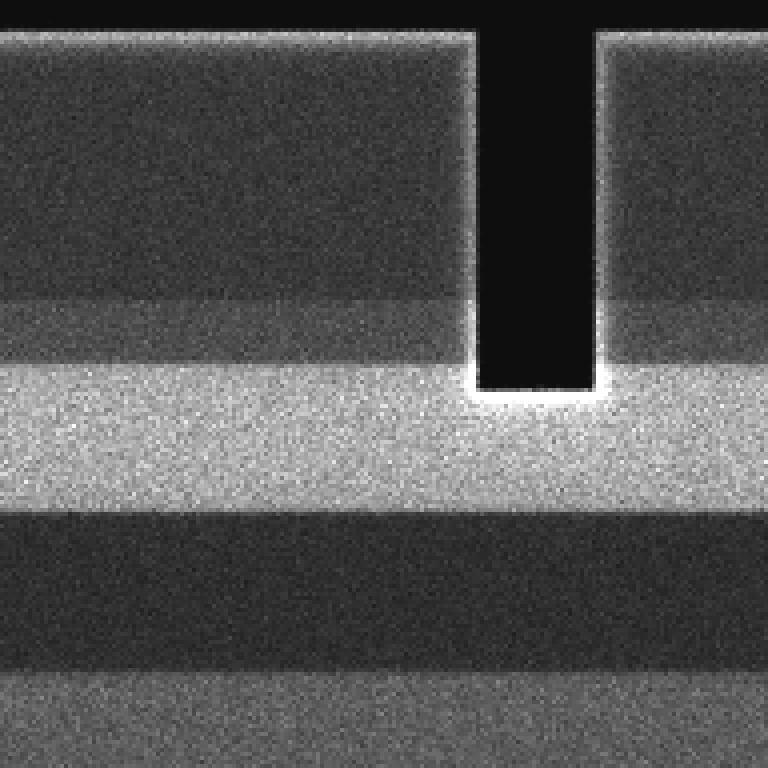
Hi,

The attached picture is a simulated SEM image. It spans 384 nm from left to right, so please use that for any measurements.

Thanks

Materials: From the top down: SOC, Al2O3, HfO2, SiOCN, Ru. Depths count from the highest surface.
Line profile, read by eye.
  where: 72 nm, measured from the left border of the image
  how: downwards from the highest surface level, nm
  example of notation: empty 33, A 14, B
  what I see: SOC 134, Al2O3 32, HfO2 74, SiOCN 80, Ru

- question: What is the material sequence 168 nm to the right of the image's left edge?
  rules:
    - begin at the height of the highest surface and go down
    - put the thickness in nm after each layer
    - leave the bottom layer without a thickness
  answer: SOC 134, Al2O3 32, HfO2 74, SiOCN 80, Ru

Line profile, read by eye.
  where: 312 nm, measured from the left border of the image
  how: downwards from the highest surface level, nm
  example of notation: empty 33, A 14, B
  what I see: SOC 134, Al2O3 32, HfO2 74, SiOCN 80, Ru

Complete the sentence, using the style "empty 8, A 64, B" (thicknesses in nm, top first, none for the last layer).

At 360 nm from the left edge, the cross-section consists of SOC 134, Al2O3 32, HfO2 74, SiOCN 80, Ru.